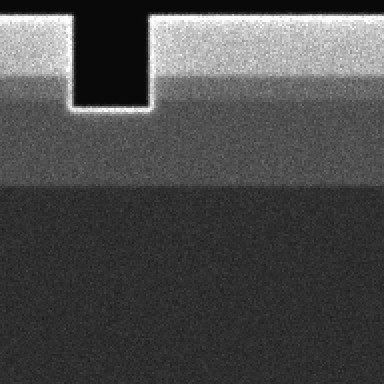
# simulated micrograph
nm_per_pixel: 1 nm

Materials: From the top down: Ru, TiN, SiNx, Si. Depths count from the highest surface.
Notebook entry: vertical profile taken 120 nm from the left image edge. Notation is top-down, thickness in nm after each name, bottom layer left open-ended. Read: empty 92, SiNx 78, Si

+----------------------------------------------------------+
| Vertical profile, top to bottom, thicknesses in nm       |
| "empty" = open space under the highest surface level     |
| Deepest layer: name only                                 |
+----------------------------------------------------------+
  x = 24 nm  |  Ru 60, TiN 24, SiNx 86, Si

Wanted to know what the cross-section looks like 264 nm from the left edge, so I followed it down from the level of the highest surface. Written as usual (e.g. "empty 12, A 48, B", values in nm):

Ru 60, TiN 24, SiNx 86, Si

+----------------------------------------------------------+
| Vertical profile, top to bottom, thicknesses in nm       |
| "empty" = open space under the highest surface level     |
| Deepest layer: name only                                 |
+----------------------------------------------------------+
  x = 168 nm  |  Ru 60, TiN 24, SiNx 86, Si